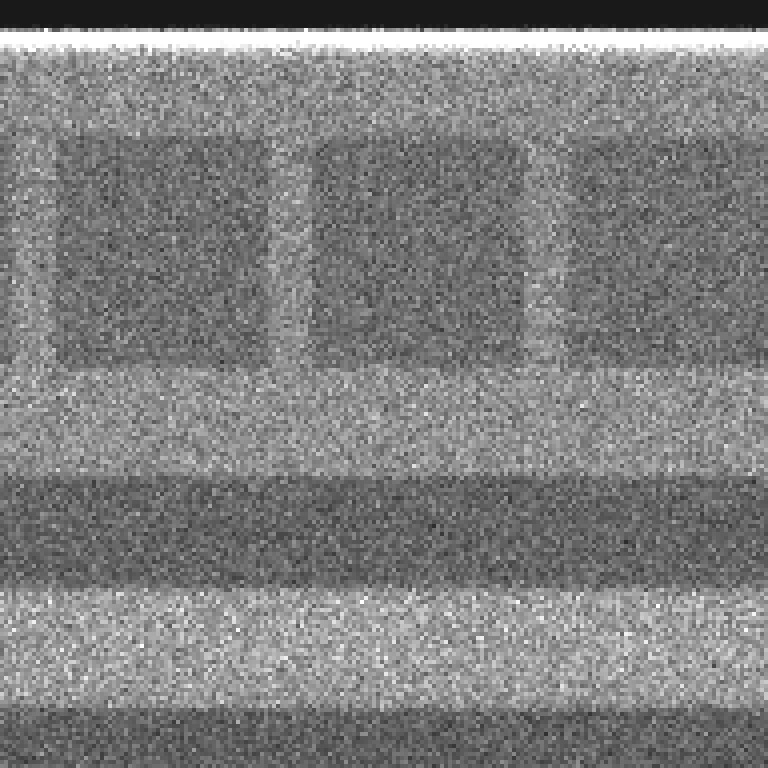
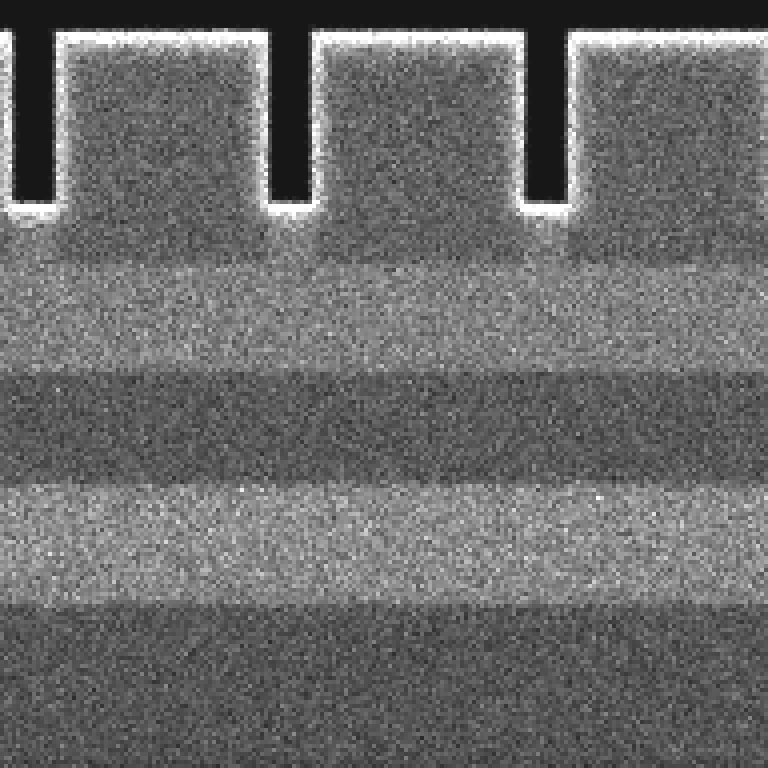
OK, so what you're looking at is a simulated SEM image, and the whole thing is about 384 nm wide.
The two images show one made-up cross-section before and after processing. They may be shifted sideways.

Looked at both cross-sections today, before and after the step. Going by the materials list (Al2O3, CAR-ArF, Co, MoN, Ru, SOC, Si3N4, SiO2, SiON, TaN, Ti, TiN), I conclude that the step removed SiO2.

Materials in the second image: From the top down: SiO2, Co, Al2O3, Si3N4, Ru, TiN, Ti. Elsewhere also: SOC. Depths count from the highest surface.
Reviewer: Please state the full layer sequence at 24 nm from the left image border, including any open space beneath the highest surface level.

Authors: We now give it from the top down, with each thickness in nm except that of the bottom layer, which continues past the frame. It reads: empty 86, SiO2 30, Co 24, Al2O3 30, Si3N4 56, Ru 60, TiN 78, Ti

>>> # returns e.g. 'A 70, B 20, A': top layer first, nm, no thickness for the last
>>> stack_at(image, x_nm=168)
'SOC 116, Al2O3 54, Si3N4 56, Ru 60, TiN 78, Ti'